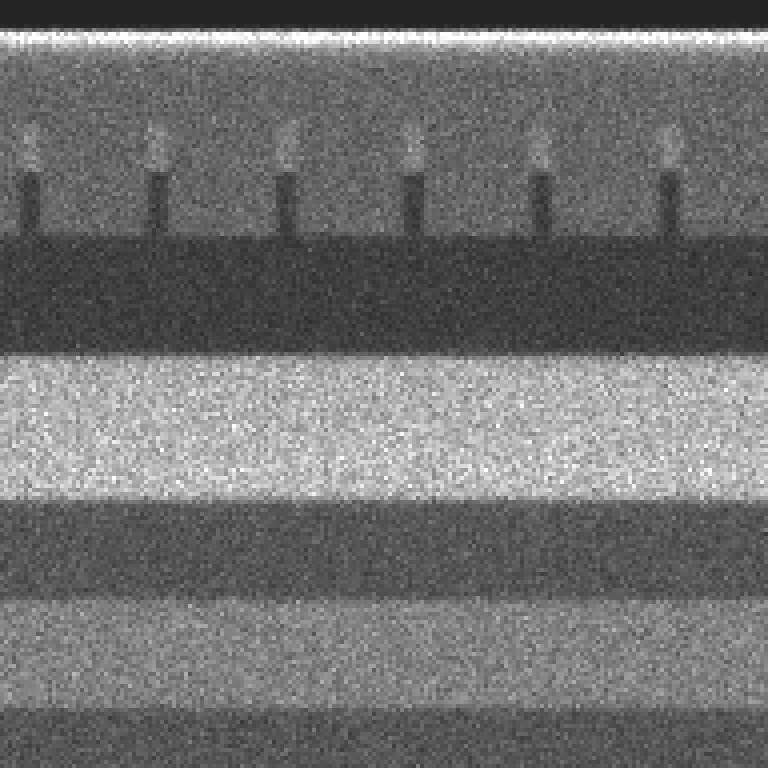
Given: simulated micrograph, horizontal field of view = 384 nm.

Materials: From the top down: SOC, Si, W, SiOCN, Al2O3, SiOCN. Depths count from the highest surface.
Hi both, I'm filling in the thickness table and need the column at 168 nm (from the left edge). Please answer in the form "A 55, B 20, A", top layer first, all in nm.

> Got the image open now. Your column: SOC 102, Si 60, W 72, SiOCN 50, Al2O3 54, SiOCN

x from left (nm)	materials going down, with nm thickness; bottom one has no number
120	SOC 102, Si 60, W 72, SiOCN 50, Al2O3 54, SiOCN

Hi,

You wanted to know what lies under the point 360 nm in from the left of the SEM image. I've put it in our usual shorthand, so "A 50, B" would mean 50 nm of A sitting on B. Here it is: SOC 102, Si 60, W 72, SiOCN 50, Al2O3 54, SiOCN